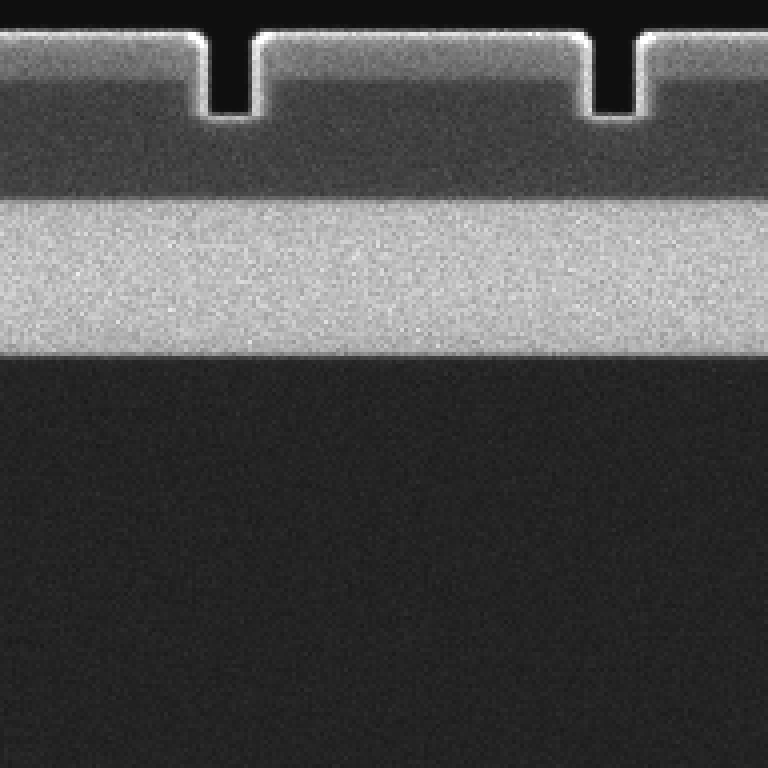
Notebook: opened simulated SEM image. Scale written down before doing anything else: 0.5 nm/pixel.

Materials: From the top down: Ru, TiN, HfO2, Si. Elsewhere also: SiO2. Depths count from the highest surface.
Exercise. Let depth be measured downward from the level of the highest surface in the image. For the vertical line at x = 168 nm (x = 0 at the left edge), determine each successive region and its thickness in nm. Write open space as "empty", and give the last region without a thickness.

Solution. Ru 24, TiN 60, HfO2 78, Si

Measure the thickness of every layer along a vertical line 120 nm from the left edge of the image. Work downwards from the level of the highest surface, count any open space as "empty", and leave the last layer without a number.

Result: empty 42, TiN 42, HfO2 78, Si